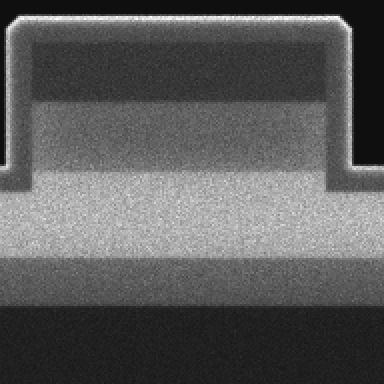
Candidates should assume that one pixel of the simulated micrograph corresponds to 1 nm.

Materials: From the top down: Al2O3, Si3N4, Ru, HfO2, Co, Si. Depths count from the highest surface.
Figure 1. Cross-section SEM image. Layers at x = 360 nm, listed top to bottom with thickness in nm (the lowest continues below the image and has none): empty 150, Al2O3 26, HfO2 66, Co 48, Si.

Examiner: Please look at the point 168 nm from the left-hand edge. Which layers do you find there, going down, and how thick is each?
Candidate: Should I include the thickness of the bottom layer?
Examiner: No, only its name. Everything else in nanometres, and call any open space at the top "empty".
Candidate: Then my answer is Al2O3 26, Si3N4 60, Ru 70, HfO2 86, Co 48, Si